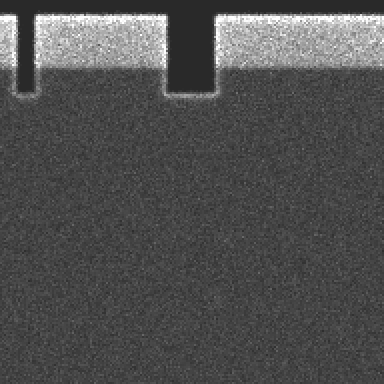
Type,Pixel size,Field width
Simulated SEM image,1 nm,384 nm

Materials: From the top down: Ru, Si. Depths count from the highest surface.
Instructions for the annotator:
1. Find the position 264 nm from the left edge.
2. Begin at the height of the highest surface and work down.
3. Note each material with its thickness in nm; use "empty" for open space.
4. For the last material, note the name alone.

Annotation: Ru 52, Si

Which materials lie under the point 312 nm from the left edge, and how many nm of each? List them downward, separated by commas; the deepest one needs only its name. Ru 52, Si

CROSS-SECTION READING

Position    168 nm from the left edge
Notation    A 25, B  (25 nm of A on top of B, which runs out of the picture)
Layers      empty 78, Si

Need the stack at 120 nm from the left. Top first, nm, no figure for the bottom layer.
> Ru 52, Si